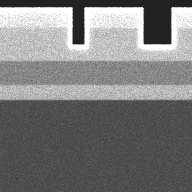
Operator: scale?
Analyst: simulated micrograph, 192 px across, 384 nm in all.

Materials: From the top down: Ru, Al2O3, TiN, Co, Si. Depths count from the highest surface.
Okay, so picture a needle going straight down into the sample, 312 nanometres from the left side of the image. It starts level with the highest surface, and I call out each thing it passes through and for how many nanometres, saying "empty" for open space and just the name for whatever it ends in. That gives empty 74, Al2O3 32, TiN 48, Co 30, Si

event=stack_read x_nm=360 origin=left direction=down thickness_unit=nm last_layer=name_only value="Ru 40, Al2O3 66, TiN 48, Co 30, Si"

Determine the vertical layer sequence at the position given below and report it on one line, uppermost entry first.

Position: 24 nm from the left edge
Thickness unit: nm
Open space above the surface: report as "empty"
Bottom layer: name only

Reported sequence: Ru 40, Al2O3 66, TiN 48, Co 30, Si